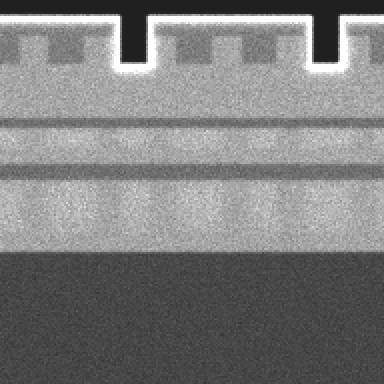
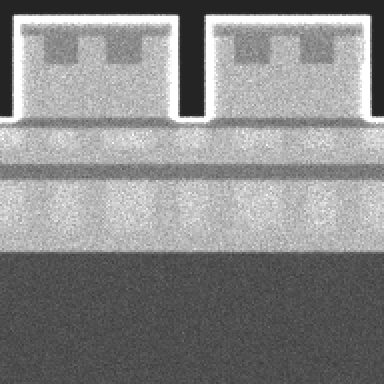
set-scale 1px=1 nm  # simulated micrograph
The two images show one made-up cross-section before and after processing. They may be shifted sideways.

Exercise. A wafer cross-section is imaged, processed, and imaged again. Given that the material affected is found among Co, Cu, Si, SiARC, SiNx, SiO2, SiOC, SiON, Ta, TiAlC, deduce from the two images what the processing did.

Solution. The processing removed SiO2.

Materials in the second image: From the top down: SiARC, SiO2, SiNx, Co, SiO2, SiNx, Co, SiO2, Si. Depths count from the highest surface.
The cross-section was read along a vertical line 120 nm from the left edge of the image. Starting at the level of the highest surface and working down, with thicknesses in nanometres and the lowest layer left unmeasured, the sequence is SiARC 48, SiO2 54, SiNx 10, Co 20, SiO2 16, SiNx 16, Co 52, SiO2 20, Si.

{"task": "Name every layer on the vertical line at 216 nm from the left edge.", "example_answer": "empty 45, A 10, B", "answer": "SiARC 20, SiO2 82, SiNx 10, SiO2 36, SiNx 16, SiO2 72, Si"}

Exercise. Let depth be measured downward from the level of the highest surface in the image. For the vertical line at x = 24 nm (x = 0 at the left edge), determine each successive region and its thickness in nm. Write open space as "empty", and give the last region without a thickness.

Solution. SiARC 20, SiO2 82, SiNx 10, Co 20, SiO2 16, SiNx 16, Co 52, SiO2 20, Si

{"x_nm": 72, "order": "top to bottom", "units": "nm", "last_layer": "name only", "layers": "SiARC 48, SiO2 54, SiNx 10, Co 20, SiO2 16, SiNx 16, Co 52, SiO2 20, Si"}